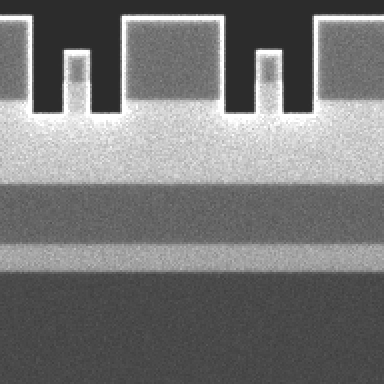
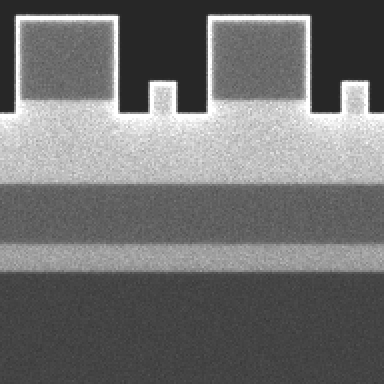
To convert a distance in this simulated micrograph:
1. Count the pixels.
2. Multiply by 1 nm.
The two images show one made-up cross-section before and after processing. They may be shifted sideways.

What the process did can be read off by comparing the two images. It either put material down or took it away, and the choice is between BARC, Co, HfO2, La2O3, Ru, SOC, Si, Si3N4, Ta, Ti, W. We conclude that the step removed SOC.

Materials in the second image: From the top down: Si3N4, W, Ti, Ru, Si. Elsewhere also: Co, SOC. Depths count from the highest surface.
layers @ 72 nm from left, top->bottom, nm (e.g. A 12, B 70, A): Si3N4 84, W 84, Ti 60, Ru 28, Si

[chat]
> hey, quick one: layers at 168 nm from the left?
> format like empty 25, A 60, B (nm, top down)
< empty 66, Co 32, W 70, Ti 60, Ru 28, Si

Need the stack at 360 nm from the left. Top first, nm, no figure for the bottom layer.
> empty 66, Co 32, W 70, Ti 60, Ru 28, Si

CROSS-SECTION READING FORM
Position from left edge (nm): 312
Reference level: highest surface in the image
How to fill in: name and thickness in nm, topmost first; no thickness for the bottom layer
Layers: empty 98, W 70, Ti 60, Ru 28, Si